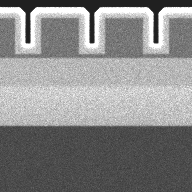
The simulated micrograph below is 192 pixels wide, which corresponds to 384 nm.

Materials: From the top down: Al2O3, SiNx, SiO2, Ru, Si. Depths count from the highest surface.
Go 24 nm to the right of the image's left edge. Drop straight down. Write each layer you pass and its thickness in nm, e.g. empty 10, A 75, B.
Al2O3 20, SiNx 80, SiO2 56, Ru 80, Si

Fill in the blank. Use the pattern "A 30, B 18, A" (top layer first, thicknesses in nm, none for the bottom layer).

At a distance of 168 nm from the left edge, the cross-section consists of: empty 2, Al2O3 90, SiNx 8, SiO2 56, Ru 80, Si